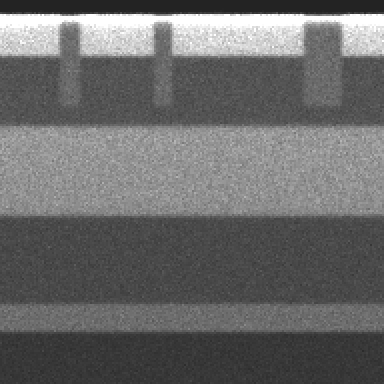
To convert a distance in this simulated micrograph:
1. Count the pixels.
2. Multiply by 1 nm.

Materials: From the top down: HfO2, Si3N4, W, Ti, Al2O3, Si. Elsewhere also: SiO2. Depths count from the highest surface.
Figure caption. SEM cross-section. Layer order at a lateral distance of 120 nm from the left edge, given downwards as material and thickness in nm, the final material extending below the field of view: HfO2 40, Si3N4 70, W 90, Ti 88, Al2O3 28, Si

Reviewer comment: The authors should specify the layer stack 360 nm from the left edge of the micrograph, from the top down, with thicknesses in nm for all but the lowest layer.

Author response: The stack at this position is HfO2 40, Si3N4 70, W 90, Ti 88, Al2O3 28, Si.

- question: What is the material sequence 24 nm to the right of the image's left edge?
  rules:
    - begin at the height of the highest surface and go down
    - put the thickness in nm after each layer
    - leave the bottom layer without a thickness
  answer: HfO2 40, Si3N4 70, W 90, Ti 88, Al2O3 28, Si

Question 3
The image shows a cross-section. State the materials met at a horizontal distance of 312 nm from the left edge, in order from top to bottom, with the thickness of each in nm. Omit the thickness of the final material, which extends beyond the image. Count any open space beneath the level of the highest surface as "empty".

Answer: SiO2 90, Si3N4 20, W 90, Ti 88, Al2O3 28, Si